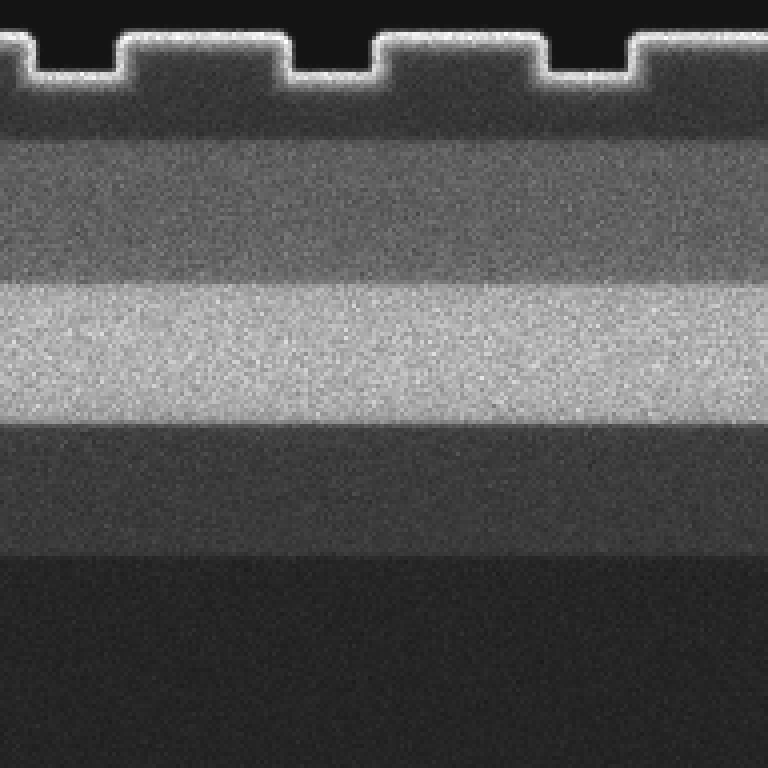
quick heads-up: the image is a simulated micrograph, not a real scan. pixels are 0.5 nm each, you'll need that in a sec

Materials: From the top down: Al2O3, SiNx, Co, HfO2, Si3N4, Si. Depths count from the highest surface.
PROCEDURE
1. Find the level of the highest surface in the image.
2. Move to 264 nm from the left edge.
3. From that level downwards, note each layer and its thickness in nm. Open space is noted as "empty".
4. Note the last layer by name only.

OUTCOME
Al2O3 30, SiNx 24, Co 72, HfO2 70, Si3N4 66, Si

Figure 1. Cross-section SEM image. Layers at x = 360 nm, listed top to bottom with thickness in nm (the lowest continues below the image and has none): Al2O3 10, SiNx 44, Co 72, HfO2 70, Si3N4 66, Si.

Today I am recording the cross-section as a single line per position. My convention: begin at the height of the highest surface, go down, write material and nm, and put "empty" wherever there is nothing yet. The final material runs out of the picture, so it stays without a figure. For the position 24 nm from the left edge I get empty 20, Al2O3 10, SiNx 24, Co 72, HfO2 70, Si3N4 66, Si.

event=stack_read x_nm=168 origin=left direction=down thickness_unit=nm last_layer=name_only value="empty 20, Al2O3 10, SiNx 24, Co 72, HfO2 70, Si3N4 66, Si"